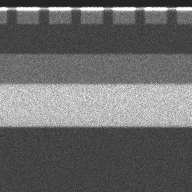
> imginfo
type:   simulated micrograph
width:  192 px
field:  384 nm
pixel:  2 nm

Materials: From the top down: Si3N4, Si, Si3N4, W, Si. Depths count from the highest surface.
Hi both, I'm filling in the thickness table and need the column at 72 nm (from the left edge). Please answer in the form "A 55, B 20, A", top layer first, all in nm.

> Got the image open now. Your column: Si3N4 32, Si 60, Si3N4 60, W 86, Si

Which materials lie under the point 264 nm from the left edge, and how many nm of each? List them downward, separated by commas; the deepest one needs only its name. Si3N4 32, Si 60, Si3N4 60, W 86, Si